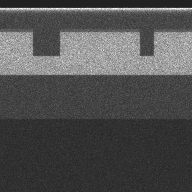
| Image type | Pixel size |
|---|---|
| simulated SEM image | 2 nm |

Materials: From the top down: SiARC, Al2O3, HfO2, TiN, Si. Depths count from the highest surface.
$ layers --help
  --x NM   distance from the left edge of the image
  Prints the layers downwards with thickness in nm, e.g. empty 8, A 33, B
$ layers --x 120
SiARC 42, Al2O3 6, HfO2 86, TiN 88, Si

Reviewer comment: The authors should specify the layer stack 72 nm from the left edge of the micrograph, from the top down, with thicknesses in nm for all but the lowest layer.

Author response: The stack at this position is SiARC 96, HfO2 38, TiN 88, Si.